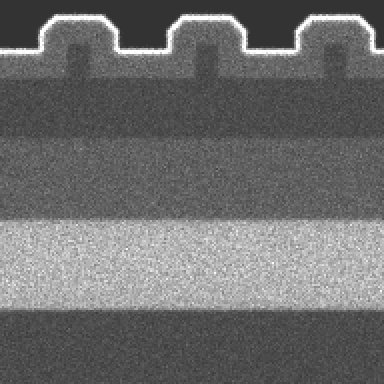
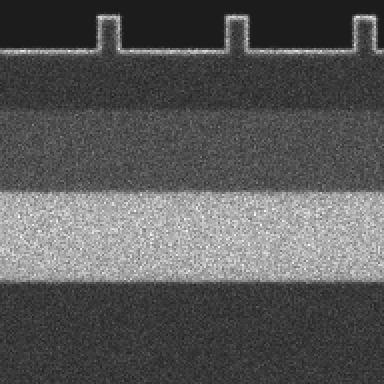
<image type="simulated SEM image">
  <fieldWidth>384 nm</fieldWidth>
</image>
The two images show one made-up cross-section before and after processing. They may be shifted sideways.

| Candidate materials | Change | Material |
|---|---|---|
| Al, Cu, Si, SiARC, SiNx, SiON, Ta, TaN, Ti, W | removed | SiNx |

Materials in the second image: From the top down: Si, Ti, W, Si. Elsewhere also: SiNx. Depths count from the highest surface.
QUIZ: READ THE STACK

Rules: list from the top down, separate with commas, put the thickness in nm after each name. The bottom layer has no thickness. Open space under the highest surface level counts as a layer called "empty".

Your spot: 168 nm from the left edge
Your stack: empty 34, Si 60, Ti 82, W 90, Si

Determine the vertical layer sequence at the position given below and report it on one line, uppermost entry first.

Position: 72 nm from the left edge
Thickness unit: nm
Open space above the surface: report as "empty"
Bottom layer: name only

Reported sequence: empty 34, Si 60, Ti 82, W 90, Si